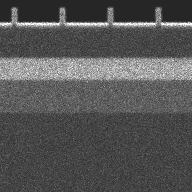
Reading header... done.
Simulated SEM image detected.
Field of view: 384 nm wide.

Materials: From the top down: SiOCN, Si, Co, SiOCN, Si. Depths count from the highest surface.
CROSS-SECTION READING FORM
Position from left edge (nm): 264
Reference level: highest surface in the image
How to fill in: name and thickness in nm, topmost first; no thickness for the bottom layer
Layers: empty 30, SiOCN 10, Si 60, Co 44, SiOCN 66, Si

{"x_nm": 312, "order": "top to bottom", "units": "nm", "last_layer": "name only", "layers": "Si 100, Co 44, SiOCN 66, Si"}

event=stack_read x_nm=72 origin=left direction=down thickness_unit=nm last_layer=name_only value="empty 30, SiOCN 10, Si 60, Co 44, SiOCN 66, Si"